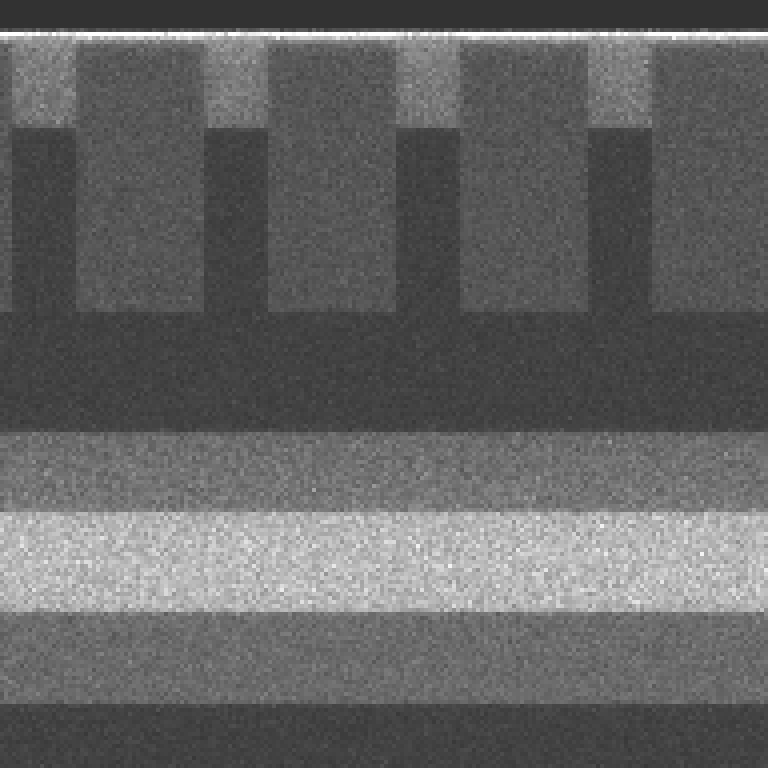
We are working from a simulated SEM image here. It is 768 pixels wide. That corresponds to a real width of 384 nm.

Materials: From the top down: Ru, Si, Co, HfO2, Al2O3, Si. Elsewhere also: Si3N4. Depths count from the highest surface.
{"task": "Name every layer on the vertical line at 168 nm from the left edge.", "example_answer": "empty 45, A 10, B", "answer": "Si3N4 140, Si 60, Co 40, HfO2 50, Al2O3 46, Si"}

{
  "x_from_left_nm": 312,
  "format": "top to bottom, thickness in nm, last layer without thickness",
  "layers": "Ru 48, Si 152, Co 40, HfO2 50, Al2O3 46, Si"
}